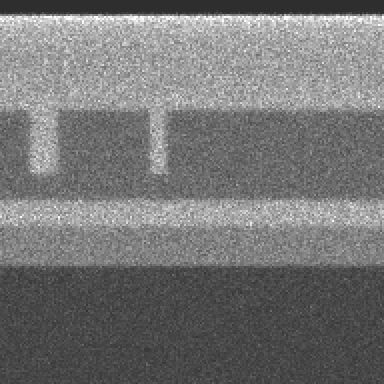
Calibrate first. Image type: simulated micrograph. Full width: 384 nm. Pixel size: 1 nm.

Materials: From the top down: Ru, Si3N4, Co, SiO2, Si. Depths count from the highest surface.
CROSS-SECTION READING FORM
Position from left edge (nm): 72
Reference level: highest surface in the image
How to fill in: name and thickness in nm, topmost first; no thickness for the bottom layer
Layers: Ru 94, Si3N4 90, Co 26, SiO2 40, Si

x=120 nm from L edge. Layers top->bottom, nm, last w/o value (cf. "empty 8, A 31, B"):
Ru 94, Si3N4 90, Co 26, SiO2 40, Si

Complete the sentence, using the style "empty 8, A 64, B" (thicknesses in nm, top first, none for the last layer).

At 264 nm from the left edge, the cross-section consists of Ru 94, Si3N4 90, Co 26, SiO2 40, Si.